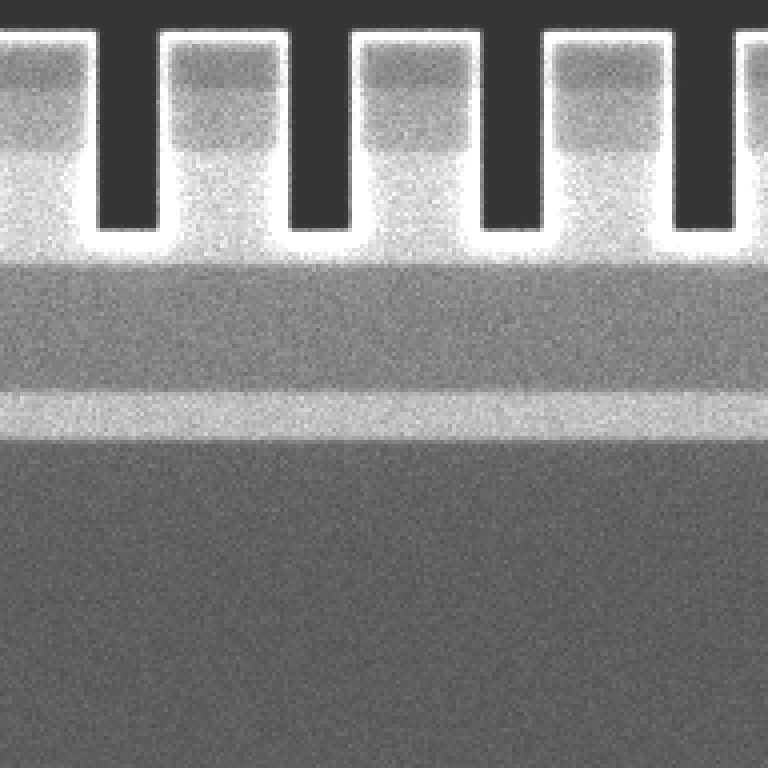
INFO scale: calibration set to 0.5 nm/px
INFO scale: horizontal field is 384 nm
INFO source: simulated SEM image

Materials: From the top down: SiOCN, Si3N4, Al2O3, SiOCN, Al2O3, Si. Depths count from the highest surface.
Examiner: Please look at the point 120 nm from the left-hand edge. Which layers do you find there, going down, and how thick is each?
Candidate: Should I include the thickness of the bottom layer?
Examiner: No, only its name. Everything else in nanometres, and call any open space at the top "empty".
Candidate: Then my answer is SiOCN 28, Si3N4 32, Al2O3 56, SiOCN 64, Al2O3 24, Si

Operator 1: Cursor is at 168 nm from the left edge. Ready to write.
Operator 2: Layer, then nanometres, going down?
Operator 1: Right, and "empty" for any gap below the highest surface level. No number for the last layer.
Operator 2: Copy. empty 100, Al2O3 16, SiOCN 64, Al2O3 24, Si